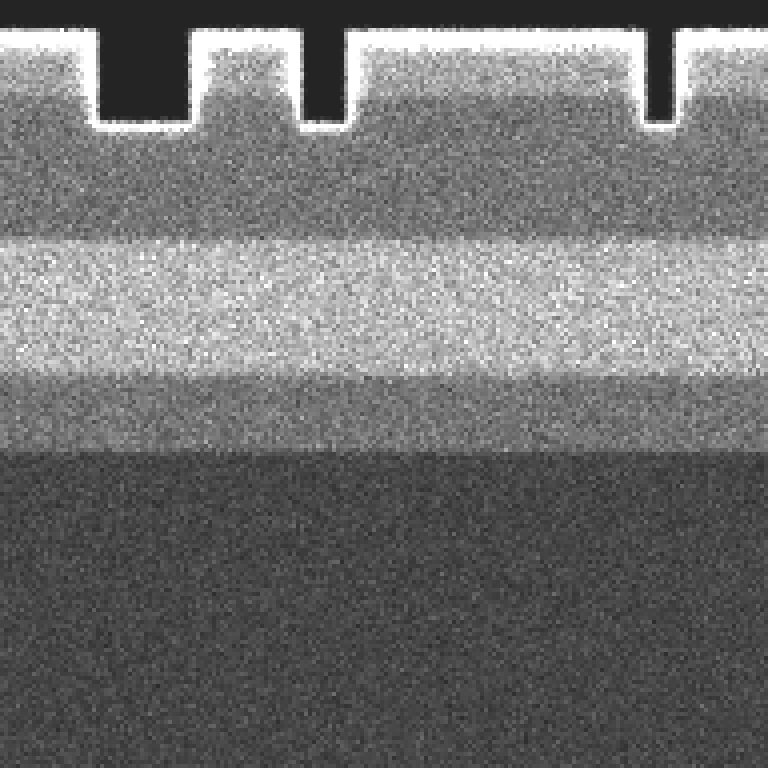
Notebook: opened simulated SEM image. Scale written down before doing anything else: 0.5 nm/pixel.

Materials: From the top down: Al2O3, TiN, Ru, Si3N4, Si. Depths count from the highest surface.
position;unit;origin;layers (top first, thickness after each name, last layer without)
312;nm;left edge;Al2O3 32, TiN 72, Ru 68, Si3N4 38, Si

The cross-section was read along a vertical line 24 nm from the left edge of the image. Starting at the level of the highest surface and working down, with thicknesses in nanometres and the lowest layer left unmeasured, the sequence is Al2O3 32, TiN 72, Ru 68, Si3N4 38, Si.